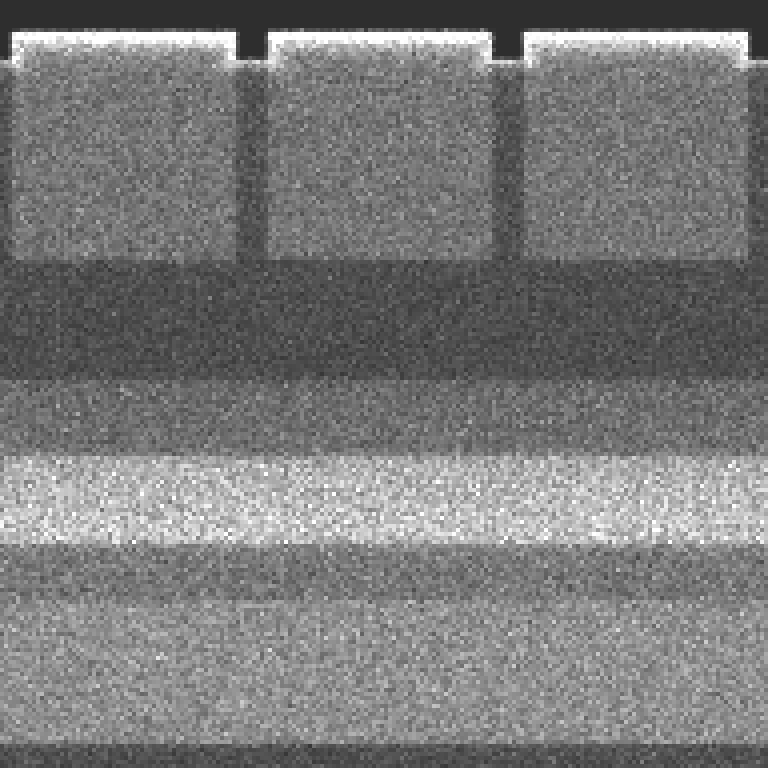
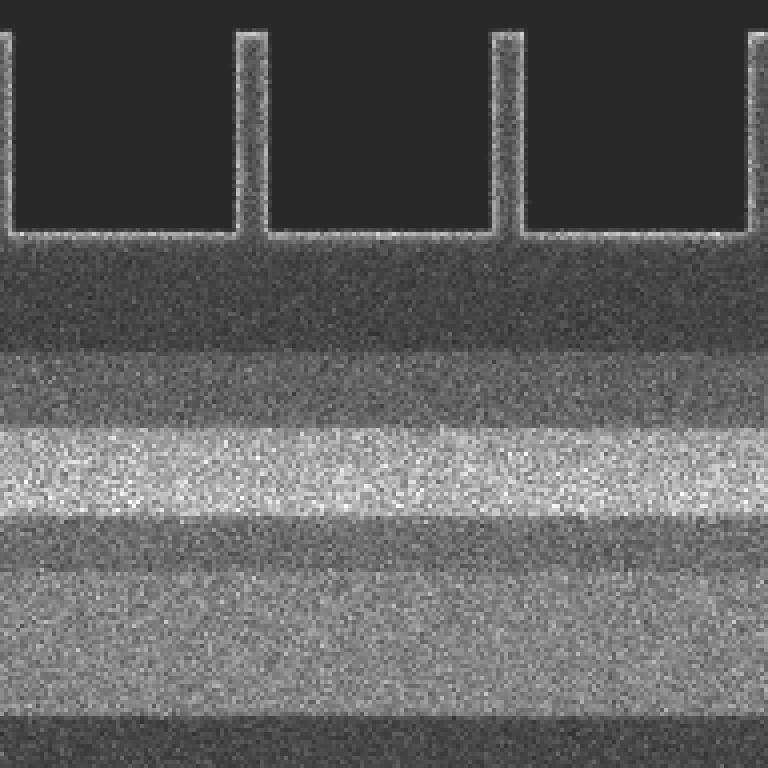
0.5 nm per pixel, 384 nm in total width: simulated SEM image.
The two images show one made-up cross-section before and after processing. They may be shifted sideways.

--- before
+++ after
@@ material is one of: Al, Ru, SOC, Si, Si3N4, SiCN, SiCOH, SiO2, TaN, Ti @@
SOC removed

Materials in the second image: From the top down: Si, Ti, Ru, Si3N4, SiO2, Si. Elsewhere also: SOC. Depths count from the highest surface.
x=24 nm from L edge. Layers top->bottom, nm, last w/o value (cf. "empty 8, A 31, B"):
empty 100, Si 60, Ti 38, Ru 44, Si3N4 28, SiO2 72, Si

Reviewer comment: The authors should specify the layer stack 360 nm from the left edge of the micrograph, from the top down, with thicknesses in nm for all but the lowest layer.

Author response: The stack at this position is empty 100, Si 60, Ti 38, Ru 44, Si3N4 28, SiO2 72, Si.